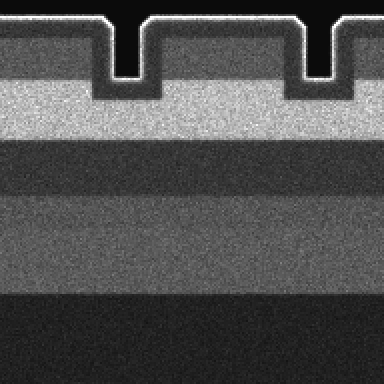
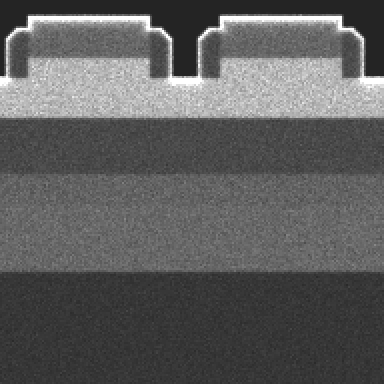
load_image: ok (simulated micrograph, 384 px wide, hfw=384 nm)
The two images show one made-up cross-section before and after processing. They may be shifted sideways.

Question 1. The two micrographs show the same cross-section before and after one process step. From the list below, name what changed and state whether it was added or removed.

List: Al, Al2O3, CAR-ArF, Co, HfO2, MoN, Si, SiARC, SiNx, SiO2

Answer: SiNx, removed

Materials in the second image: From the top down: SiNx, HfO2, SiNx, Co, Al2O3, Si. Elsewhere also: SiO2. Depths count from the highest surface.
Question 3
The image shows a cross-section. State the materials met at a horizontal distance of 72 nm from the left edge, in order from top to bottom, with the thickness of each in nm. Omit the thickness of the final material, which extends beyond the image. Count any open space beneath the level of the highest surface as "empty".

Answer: SiO2 42, HfO2 60, SiNx 56, Co 32, Al2O3 66, Si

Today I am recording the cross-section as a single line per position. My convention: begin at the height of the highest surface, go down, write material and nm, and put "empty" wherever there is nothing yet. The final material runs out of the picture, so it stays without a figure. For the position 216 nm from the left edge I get empty 12, SiNx 50, HfO2 40, SiNx 56, Co 32, Al2O3 66, Si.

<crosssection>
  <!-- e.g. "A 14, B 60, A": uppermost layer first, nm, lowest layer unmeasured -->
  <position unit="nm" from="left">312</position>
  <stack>SiO2 42, HfO2 60, SiNx 56, Co 32, Al2O3 66, Si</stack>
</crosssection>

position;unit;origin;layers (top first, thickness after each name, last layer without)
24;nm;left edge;empty 12, SiNx 50, HfO2 40, SiNx 56, Co 32, Al2O3 66, Si